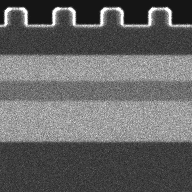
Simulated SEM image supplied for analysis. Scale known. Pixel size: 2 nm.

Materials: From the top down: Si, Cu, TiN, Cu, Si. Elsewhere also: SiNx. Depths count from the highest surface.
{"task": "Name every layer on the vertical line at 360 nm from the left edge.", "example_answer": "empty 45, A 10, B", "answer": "empty 34, Si 60, Cu 52, TiN 40, Cu 82, Si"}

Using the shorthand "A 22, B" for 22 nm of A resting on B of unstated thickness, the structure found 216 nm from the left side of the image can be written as Si 94, Cu 52, TiN 40, Cu 82, Si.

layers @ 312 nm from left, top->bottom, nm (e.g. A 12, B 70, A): Si 94, Cu 52, TiN 40, Cu 82, Si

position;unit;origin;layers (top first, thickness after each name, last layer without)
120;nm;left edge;Si 94, Cu 52, TiN 40, Cu 82, Si